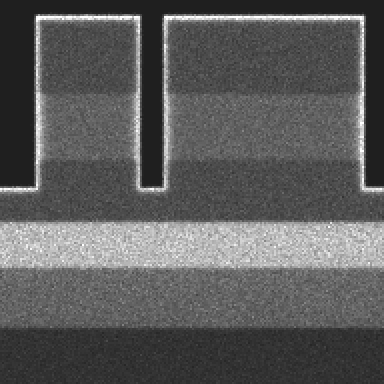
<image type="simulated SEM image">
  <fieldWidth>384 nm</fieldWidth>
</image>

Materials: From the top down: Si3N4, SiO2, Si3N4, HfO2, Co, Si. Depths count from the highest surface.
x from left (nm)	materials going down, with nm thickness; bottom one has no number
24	empty 172, Si3N4 34, HfO2 46, Co 60, Si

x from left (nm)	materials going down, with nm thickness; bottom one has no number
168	Si3N4 78, SiO2 66, Si3N4 62, HfO2 46, Co 60, Si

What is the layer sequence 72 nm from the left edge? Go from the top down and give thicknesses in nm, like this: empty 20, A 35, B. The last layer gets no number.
Si3N4 78, SiO2 66, Si3N4 62, HfO2 46, Co 60, Si